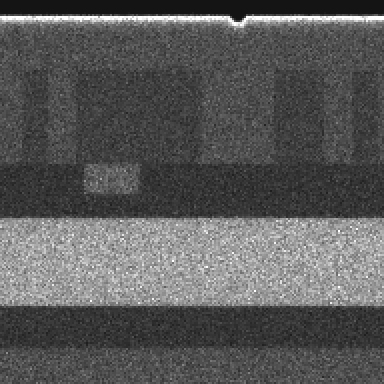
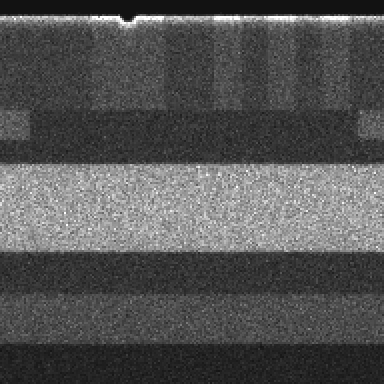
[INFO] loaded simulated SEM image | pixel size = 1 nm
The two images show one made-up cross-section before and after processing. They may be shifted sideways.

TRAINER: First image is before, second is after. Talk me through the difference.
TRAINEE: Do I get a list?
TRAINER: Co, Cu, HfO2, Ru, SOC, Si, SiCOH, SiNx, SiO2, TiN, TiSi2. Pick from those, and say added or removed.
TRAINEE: removed: SiO2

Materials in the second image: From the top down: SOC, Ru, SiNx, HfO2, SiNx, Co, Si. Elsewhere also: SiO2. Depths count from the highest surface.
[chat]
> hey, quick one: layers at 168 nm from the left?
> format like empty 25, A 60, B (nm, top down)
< SOC 94, SiNx 54, HfO2 88, SiNx 42, Co 50, Si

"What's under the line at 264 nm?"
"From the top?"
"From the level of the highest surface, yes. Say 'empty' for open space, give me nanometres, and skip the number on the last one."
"SOC 94, SiNx 54, HfO2 88, SiNx 42, Co 50, Si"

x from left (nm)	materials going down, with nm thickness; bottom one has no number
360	SOC 94, Ru 30, SiNx 24, HfO2 88, SiNx 42, Co 50, Si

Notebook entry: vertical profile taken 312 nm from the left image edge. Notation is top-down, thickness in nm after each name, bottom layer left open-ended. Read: SOC 94, SiNx 54, HfO2 88, SiNx 42, Co 50, Si